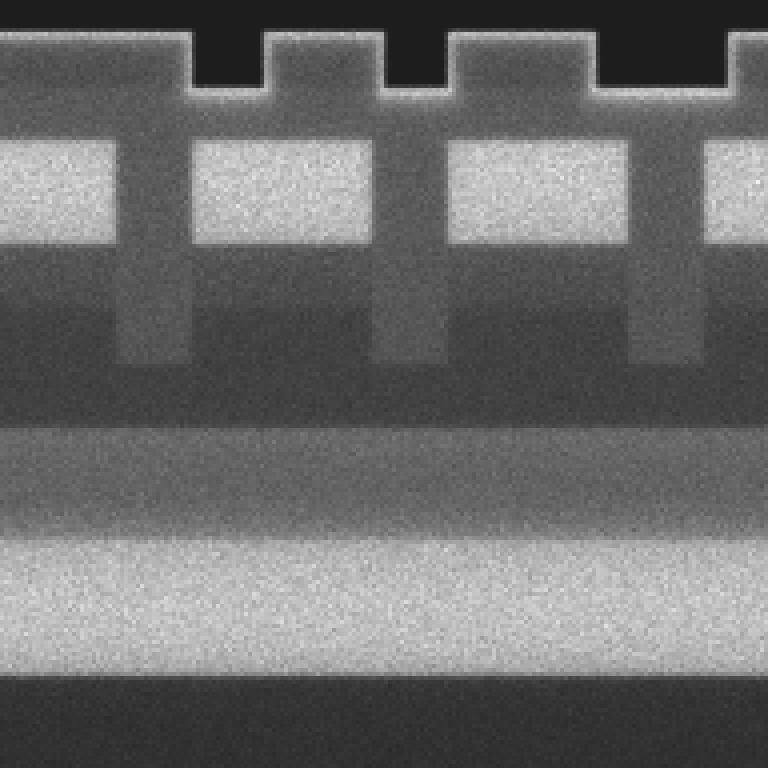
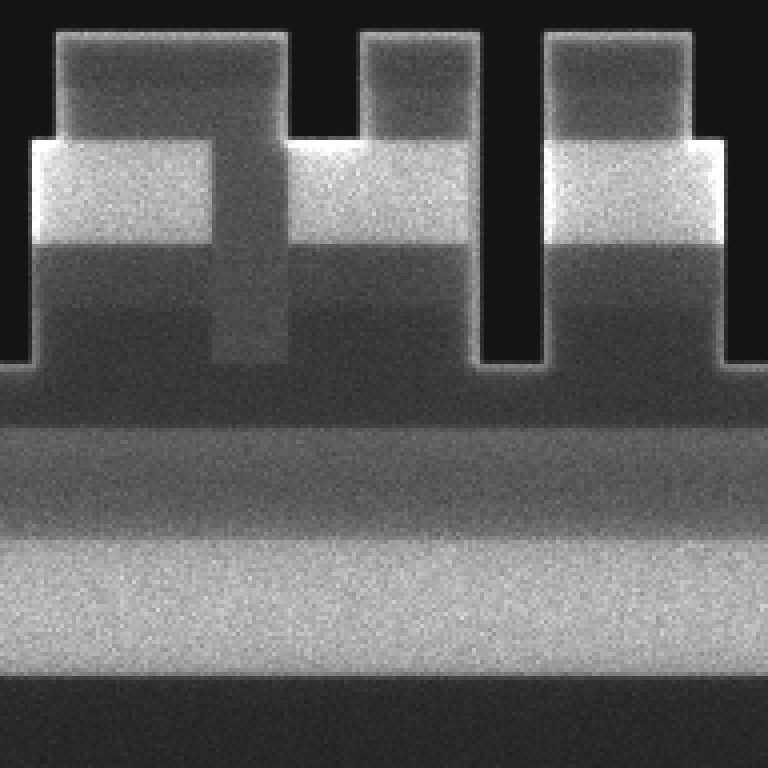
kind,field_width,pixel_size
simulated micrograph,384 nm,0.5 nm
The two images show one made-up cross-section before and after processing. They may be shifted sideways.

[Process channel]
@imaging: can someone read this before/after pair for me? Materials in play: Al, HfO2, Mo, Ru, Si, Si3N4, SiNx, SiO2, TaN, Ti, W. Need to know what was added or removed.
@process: SiO2 removed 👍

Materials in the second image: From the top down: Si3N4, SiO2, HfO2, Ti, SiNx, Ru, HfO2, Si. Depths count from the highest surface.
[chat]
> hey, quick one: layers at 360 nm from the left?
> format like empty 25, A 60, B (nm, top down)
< empty 54, HfO2 52, Ti 32, SiNx 60, Ru 56, HfO2 68, Si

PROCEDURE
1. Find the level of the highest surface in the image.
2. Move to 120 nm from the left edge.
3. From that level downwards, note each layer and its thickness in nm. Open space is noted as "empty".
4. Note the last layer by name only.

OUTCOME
Si3N4 28, SiO2 138, SiNx 32, Ru 56, HfO2 68, Si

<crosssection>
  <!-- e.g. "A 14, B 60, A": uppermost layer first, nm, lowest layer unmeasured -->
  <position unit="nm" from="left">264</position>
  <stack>empty 166, SiNx 32, Ru 56, HfO2 68, Si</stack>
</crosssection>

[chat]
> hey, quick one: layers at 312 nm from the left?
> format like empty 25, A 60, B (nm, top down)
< Si3N4 28, SiO2 26, HfO2 52, Ti 32, SiNx 60, Ru 56, HfO2 68, Si